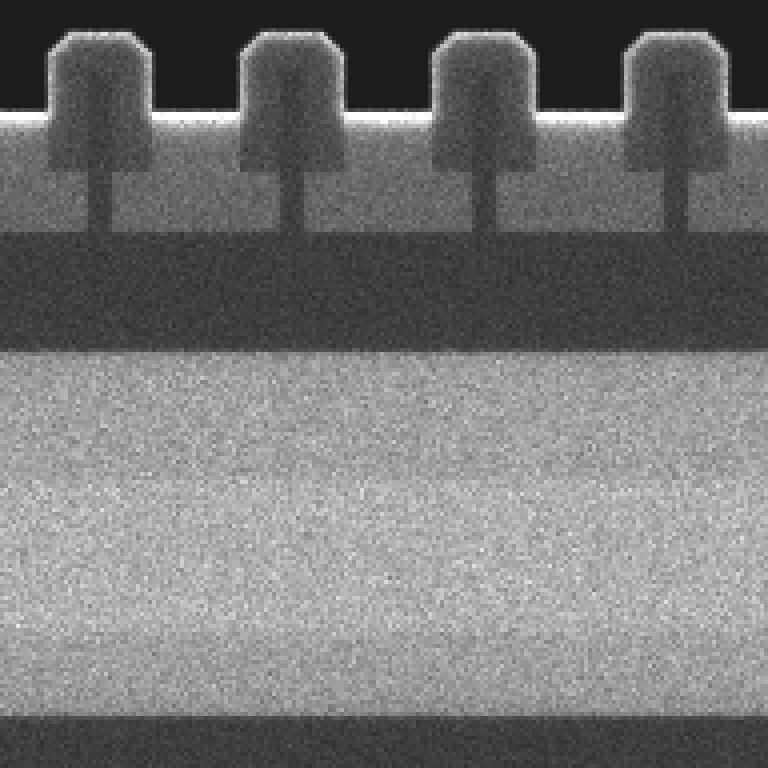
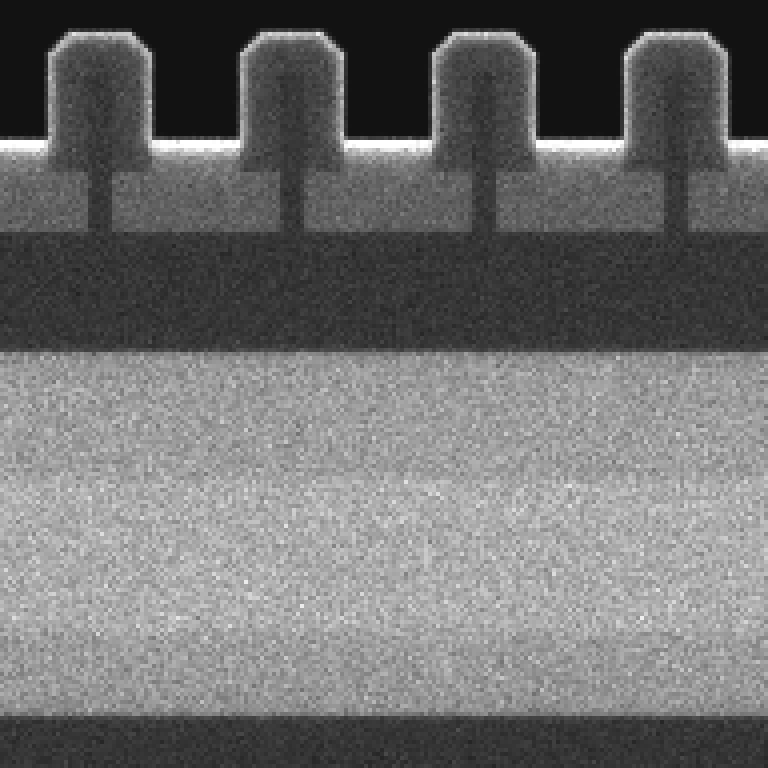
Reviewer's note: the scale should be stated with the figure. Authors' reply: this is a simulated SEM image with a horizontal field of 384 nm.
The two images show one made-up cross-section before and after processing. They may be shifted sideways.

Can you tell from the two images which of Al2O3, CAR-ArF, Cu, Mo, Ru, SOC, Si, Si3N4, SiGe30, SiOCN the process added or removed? Yes, it removed SOC.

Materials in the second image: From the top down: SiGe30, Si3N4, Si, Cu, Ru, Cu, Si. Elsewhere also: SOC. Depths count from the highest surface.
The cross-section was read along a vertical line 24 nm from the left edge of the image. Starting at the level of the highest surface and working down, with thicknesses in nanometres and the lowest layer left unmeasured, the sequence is empty 10, SiGe30 60, Si3N4 30, Si 60, Cu 64, Ru 76, Cu 42, Si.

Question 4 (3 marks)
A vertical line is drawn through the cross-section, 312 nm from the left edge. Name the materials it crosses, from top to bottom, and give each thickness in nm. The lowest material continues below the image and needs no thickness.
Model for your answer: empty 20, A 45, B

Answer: empty 10, SiGe30 60, Si3N4 30, Si 60, Cu 64, Ru 76, Cu 42, Si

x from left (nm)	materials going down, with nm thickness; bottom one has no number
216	empty 10, SiGe30 60, Si3N4 30, Si 60, Cu 64, Ru 76, Cu 42, Si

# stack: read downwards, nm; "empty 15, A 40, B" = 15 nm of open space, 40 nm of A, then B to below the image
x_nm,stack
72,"empty 8, SiGe30 62, Si3N4 30, Si 60, Cu 64, Ru 76, Cu 42, Si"